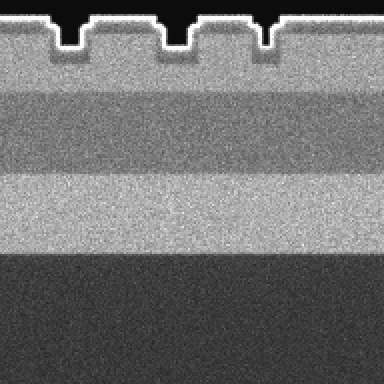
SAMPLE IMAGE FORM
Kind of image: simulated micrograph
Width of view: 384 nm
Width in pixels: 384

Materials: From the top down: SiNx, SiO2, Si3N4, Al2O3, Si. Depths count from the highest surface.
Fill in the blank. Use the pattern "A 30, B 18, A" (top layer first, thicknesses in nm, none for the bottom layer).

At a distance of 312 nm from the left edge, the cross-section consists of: SiNx 18, SiO2 58, Si3N4 82, Al2O3 80, Si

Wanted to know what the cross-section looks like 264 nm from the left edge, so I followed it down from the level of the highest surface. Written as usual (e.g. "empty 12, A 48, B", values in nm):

empty 30, SiNx 18, SiO2 28, Si3N4 82, Al2O3 80, Si